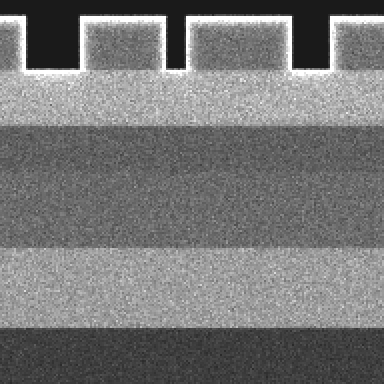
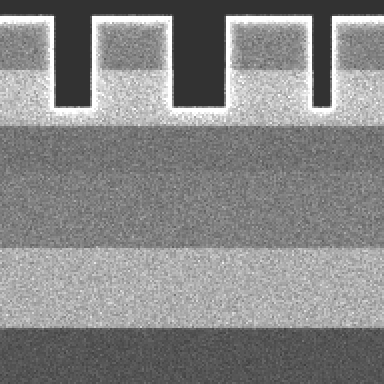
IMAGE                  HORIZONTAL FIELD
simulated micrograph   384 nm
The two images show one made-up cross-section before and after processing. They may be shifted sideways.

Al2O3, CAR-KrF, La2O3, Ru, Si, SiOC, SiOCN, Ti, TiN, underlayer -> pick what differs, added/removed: Ru removed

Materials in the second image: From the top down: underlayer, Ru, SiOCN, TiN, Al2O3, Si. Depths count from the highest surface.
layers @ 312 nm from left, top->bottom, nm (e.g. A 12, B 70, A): empty 92, Ru 18, SiOCN 46, TiN 76, Al2O3 80, Si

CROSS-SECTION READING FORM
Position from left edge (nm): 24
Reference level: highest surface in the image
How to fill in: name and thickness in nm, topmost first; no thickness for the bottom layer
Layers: underlayer 54, Ru 56, SiOCN 46, TiN 76, Al2O3 80, Si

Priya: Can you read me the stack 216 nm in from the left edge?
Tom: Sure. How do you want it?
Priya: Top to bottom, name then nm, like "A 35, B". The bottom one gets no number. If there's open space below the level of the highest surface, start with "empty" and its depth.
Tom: empty 92, Ru 18, SiOCN 46, TiN 76, Al2O3 80, Si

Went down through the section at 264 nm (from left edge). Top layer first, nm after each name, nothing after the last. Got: underlayer 54, Ru 56, SiOCN 46, TiN 76, Al2O3 80, Si